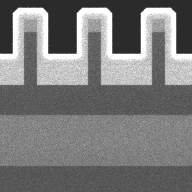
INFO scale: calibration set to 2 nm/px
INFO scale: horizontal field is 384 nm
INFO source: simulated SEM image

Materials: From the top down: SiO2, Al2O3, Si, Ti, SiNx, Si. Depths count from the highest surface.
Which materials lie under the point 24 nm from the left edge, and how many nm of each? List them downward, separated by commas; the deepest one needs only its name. empty 92, SiO2 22, Al2O3 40, Si 60, Ti 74, SiNx 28, Si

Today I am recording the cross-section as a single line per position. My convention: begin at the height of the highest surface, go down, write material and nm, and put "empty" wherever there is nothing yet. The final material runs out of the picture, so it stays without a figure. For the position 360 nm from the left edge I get empty 92, SiO2 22, Al2O3 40, Si 60, Ti 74, SiNx 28, Si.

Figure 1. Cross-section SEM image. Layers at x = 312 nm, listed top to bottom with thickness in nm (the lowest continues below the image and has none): SiO2 22, Ti 26, Si 166, Ti 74, SiNx 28, Si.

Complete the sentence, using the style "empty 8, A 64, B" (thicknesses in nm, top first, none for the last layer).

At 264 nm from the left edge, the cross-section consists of empty 92, SiO2 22, Al2O3 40, Si 60, Ti 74, SiNx 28, Si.